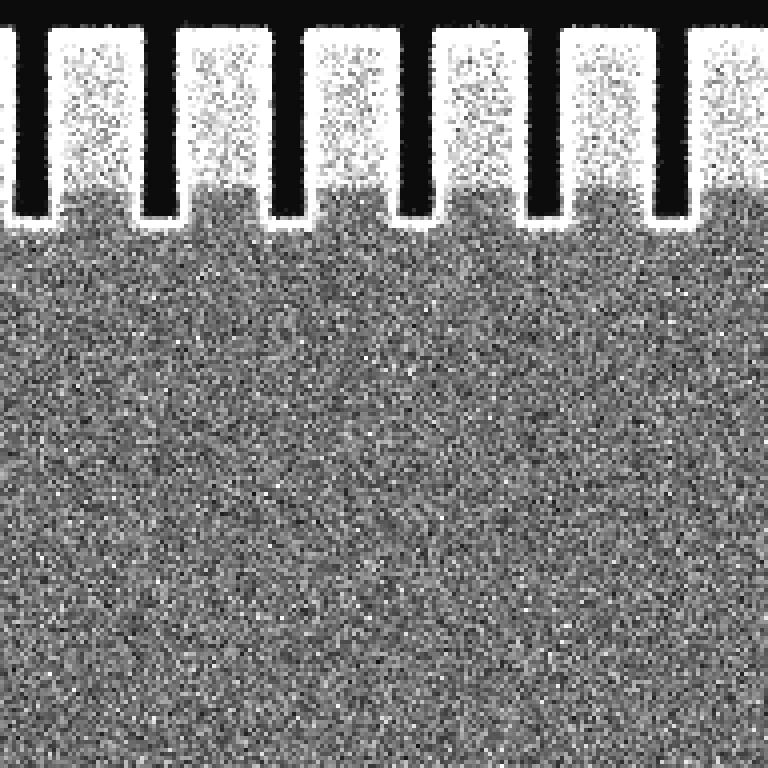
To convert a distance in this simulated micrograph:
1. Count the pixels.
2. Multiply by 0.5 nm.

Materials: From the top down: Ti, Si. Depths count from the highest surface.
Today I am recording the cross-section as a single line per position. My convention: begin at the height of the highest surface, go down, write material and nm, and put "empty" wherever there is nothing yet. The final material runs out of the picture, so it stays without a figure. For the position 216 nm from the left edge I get empty 94, Si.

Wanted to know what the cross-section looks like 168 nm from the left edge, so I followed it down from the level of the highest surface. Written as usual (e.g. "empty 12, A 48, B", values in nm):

Ti 78, Si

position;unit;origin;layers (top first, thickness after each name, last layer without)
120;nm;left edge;Ti 78, Si